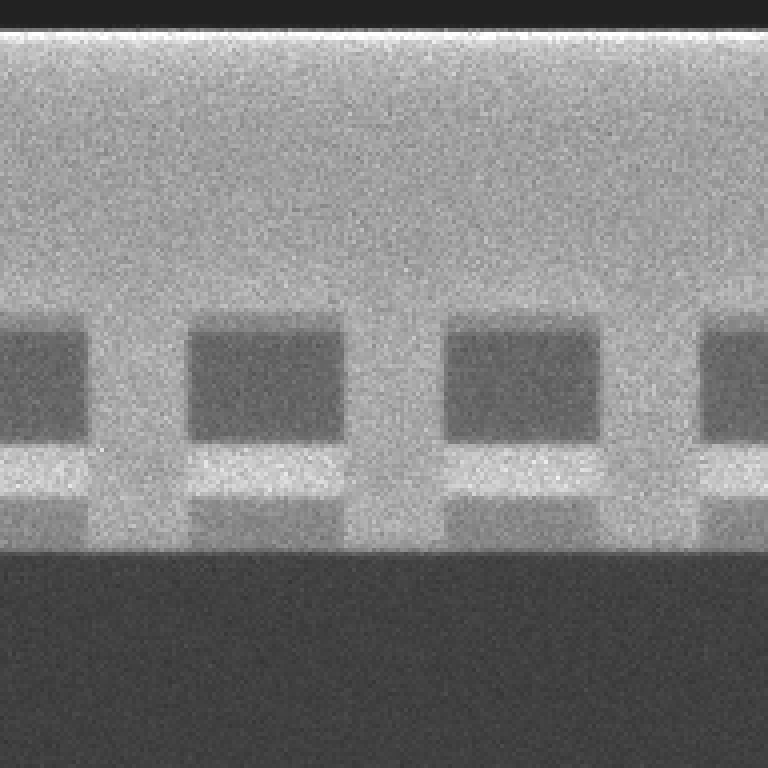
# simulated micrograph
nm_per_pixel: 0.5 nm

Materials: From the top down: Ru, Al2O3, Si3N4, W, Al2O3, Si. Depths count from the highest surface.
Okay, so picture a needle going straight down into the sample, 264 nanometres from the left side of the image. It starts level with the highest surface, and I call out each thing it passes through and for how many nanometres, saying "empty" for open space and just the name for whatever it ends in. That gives Ru 140, Al2O3 10, Si3N4 56, W 26, Al2O3 28, Si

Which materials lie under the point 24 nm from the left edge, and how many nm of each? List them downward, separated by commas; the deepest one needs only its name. Ru 140, Al2O3 10, Si3N4 56, W 26, Al2O3 28, Si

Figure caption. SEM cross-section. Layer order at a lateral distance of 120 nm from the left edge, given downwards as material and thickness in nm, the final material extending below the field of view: Ru 140, Al2O3 10, Si3N4 56, W 26, Al2O3 28, Si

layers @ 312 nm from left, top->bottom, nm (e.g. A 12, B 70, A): Ru 260, Si